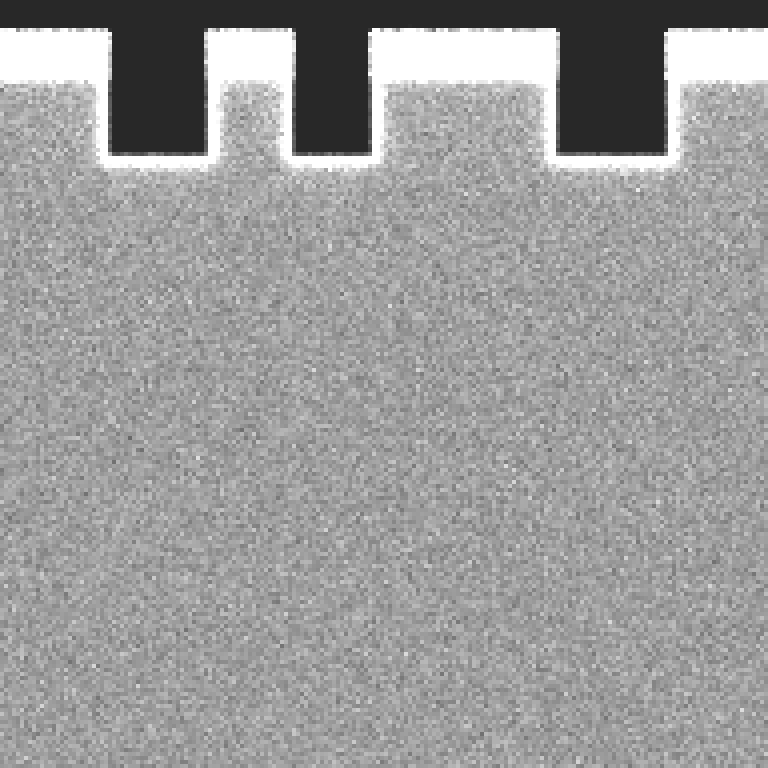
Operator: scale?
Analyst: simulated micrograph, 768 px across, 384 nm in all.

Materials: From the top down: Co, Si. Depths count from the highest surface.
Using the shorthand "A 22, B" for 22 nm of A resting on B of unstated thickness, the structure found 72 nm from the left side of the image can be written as empty 62, Si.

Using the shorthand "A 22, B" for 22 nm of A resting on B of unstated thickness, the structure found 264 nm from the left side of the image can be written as Co 24, Si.